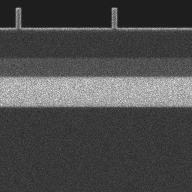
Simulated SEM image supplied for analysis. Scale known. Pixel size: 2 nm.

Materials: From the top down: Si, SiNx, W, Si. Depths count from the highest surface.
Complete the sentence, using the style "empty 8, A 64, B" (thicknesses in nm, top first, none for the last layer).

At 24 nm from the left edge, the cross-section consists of empty 40, Si 60, SiNx 38, W 60, Si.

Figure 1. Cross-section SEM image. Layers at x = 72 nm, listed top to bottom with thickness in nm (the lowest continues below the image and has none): empty 40, Si 60, SiNx 38, W 60, Si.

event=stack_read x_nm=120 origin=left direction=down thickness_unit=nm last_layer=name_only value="empty 40, Si 60, SiNx 38, W 60, Si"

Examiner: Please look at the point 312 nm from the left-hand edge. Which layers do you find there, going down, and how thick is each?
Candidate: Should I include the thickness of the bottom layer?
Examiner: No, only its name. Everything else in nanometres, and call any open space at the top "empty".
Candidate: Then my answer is empty 40, Si 60, SiNx 38, W 60, Si